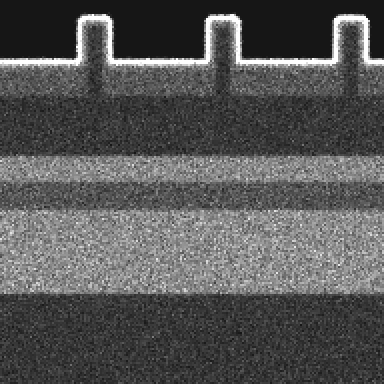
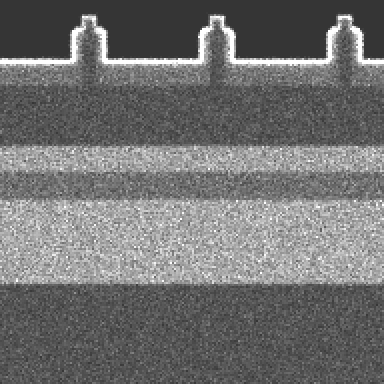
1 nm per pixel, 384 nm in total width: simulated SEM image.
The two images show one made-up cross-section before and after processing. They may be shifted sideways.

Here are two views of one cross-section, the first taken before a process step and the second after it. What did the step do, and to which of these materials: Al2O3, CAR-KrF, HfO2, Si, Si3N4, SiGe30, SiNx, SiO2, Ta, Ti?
It removed Si3N4.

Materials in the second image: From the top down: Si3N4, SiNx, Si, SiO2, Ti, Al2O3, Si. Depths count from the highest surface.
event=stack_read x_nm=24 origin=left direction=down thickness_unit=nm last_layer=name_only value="empty 44, SiNx 26, Si 60, SiO2 26, Ti 28, Al2O3 84, Si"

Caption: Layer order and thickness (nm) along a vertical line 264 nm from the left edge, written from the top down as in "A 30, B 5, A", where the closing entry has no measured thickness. empty 44, SiNx 26, Si 60, SiO2 26, Ti 28, Al2O3 84, Si